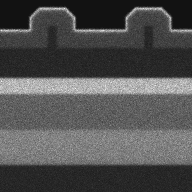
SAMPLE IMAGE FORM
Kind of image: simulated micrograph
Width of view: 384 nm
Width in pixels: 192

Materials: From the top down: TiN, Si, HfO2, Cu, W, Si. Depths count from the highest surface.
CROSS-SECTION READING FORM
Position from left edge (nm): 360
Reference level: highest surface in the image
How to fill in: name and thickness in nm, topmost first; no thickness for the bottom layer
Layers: empty 44, TiN 36, Si 60, HfO2 32, Cu 72, W 70, Si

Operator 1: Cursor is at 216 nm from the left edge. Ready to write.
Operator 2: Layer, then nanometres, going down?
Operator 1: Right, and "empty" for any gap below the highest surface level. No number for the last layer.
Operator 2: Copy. empty 44, TiN 36, Si 60, HfO2 32, Cu 72, W 70, Si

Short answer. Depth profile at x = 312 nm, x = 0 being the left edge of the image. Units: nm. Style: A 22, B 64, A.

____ TiN 80, Si 60, HfO2 32, Cu 72, W 70, Si